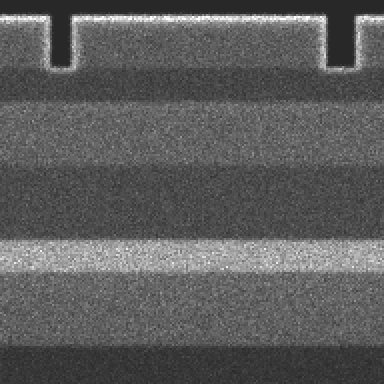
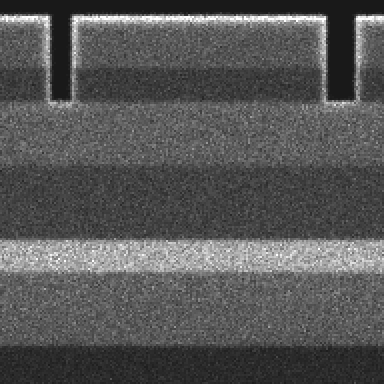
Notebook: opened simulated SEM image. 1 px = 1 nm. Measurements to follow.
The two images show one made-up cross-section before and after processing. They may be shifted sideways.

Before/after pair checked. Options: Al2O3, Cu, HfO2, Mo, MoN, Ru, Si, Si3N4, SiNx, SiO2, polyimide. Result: removed SiNx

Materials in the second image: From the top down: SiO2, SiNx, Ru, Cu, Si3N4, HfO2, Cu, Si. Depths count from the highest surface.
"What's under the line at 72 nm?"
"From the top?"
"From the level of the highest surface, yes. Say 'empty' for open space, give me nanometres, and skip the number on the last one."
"SiO2 52, SiNx 34, Ru 8, Cu 56, Si3N4 74, HfO2 32, Cu 74, Si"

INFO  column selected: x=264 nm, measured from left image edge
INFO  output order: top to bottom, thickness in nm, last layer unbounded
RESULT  SiO2 52, SiNx 34, Ru 8, Cu 56, Si3N4 74, HfO2 32, Cu 74, Si